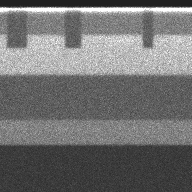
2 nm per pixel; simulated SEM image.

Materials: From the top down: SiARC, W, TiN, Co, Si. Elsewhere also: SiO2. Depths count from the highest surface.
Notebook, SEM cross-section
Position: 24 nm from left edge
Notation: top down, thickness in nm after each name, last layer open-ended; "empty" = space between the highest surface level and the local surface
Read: SiARC 80, W 54, TiN 90, Co 50, Si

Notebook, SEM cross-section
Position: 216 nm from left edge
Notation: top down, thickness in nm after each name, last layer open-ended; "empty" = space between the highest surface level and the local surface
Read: SiO2 54, W 80, TiN 90, Co 50, Si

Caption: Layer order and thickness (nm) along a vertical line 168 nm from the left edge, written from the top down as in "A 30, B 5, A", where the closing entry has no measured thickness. SiO2 54, W 80, TiN 90, Co 50, Si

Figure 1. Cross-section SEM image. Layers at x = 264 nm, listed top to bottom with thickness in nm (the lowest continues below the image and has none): SiO2 54, W 80, TiN 90, Co 50, Si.